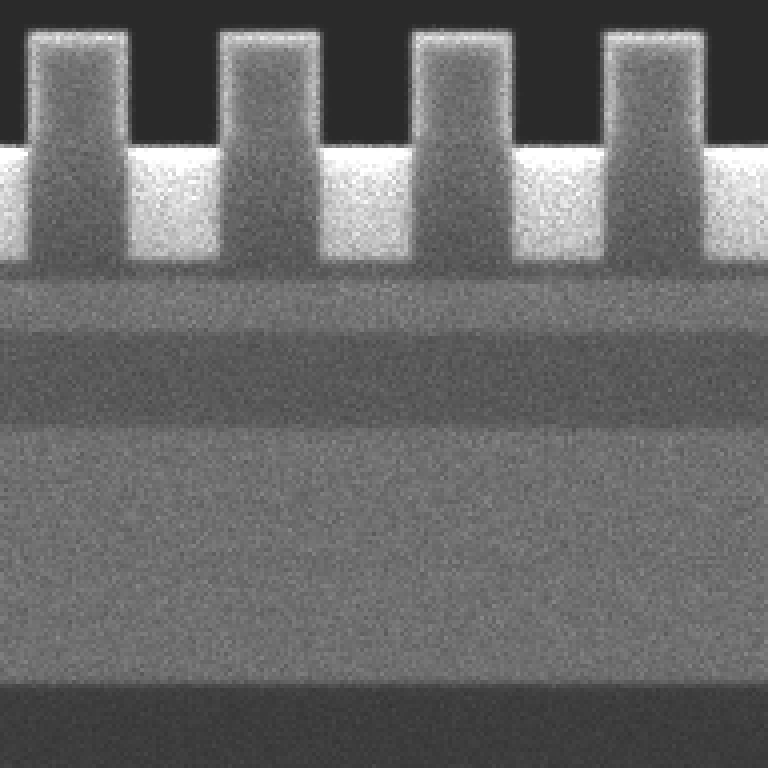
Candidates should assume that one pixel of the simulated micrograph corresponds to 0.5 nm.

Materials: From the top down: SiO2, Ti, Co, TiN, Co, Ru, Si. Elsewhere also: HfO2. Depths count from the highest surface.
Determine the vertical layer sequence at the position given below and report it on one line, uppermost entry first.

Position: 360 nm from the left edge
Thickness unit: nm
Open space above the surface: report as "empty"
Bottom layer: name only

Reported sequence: empty 58, HfO2 56, Ti 10, Co 26, TiN 48, Co 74, Ru 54, Si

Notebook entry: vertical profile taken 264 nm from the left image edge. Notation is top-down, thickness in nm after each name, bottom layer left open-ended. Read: empty 58, HfO2 56, Ti 10, Co 26, TiN 48, Co 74, Ru 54, Si